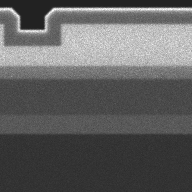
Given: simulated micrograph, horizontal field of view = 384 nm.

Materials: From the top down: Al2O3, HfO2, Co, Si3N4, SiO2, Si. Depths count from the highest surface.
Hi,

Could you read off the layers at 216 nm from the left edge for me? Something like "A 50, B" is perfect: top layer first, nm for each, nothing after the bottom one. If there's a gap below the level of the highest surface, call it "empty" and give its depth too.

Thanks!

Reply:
Al2O3 32, HfO2 84, Co 26, Si3N4 72, SiO2 38, Si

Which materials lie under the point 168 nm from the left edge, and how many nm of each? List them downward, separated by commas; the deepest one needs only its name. Al2O3 32, HfO2 84, Co 26, Si3N4 72, SiO2 38, Si